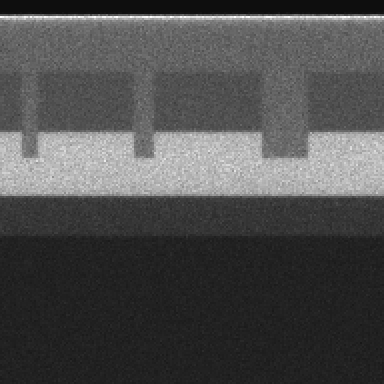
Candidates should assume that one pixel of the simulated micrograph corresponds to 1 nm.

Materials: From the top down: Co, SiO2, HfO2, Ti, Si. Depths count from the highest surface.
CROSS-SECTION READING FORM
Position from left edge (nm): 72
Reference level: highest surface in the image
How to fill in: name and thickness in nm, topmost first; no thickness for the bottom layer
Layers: Co 56, SiO2 60, HfO2 64, Ti 40, Si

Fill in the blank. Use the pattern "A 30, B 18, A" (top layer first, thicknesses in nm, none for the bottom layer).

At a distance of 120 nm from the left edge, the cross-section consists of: Co 56, SiO2 60, HfO2 64, Ti 40, Si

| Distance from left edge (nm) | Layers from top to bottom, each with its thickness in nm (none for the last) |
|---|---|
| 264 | Co 142, HfO2 38, Ti 40, Si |